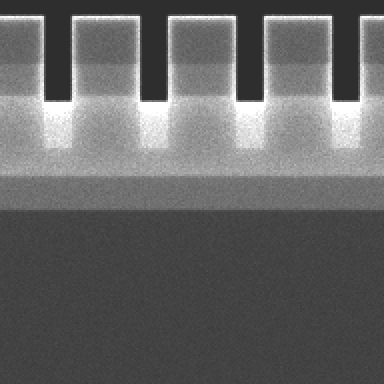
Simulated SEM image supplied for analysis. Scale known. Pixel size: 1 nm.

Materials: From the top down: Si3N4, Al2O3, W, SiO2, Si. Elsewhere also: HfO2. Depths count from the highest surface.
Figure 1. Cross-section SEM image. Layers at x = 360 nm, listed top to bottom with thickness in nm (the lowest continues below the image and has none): Si3N4 48, Al2O3 32, W 80, SiO2 34, Si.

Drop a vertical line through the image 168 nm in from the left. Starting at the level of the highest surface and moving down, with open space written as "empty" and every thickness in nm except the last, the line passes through Si3N4 48, Al2O3 32, W 80, SiO2 34, Si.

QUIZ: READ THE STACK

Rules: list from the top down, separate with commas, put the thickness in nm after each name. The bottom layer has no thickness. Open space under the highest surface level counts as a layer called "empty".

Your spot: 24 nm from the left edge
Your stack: Si3N4 48, Al2O3 32, W 80, SiO2 34, Si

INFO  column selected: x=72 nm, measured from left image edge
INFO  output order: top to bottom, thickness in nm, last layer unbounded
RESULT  Si3N4 48, Al2O3 32, W 80, SiO2 34, Si